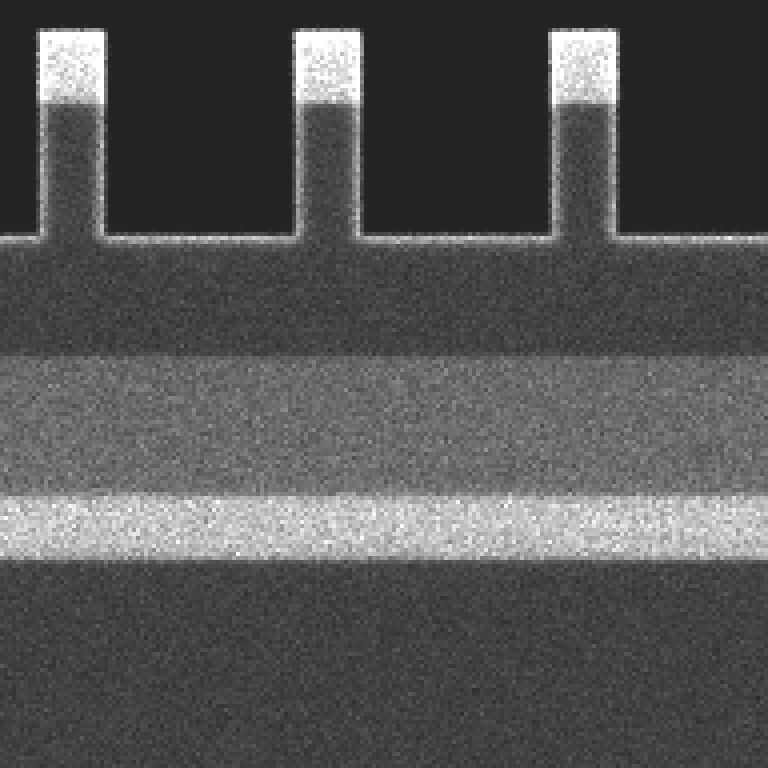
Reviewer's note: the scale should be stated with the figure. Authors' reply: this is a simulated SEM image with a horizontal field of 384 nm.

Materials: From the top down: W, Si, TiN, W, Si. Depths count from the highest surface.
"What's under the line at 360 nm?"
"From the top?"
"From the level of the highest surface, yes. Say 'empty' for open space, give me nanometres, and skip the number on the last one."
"empty 102, Si 60, TiN 70, W 32, Si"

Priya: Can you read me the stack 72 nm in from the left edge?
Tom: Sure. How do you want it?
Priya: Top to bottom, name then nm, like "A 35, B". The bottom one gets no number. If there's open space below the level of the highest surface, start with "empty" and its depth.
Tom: empty 102, Si 60, TiN 70, W 32, Si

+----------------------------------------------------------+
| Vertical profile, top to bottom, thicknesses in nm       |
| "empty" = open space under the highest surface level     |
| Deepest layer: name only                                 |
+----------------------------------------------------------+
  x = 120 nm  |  empty 102, Si 60, TiN 70, W 32, Si